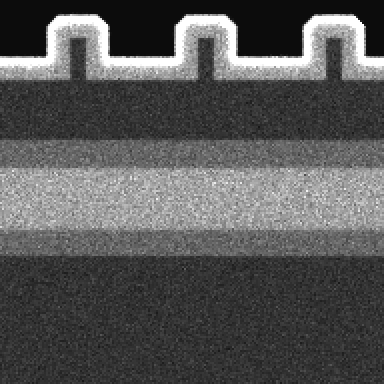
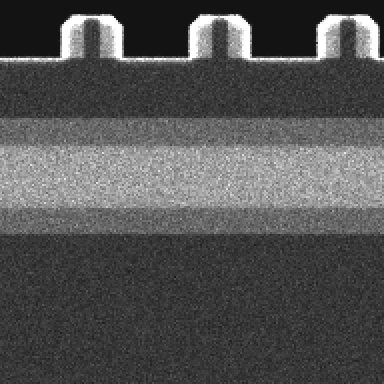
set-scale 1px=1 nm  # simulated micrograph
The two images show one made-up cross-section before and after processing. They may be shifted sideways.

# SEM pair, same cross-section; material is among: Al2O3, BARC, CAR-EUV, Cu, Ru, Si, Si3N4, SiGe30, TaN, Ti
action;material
removed;Al2O3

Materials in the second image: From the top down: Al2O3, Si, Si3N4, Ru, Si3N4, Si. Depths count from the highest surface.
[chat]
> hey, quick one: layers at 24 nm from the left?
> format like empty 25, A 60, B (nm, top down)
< empty 42, Si 60, Si3N4 28, Ru 62, Si3N4 26, Si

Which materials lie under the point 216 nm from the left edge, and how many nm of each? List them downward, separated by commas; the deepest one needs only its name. Si 102, Si3N4 28, Ru 62, Si3N4 26, Si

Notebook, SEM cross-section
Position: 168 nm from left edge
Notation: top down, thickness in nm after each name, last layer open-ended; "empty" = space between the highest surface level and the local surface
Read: empty 42, Si 60, Si3N4 28, Ru 62, Si3N4 26, Si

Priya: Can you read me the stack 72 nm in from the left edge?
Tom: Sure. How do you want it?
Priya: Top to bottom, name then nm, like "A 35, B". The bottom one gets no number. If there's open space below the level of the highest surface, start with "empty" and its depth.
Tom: Al2O3 42, Si 60, Si3N4 28, Ru 62, Si3N4 26, Si